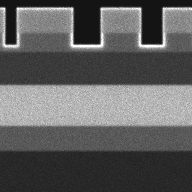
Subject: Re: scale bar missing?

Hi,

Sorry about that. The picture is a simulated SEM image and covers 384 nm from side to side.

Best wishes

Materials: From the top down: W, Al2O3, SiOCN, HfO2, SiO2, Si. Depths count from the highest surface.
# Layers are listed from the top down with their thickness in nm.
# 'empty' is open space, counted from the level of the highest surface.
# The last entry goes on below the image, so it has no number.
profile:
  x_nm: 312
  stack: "empty 74, Al2O3 14, SiOCN 66, HfO2 82, SiO2 50, Si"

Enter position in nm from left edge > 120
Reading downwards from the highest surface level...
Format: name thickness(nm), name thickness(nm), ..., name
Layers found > W 50, Al2O3 38, SiOCN 66, HfO2 82, SiO2 50, Si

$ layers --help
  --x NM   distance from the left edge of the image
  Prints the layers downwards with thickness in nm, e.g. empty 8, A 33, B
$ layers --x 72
W 50, Al2O3 38, SiOCN 66, HfO2 82, SiO2 50, Si